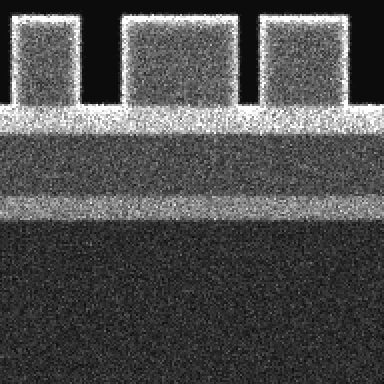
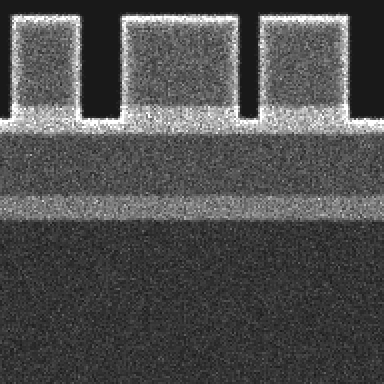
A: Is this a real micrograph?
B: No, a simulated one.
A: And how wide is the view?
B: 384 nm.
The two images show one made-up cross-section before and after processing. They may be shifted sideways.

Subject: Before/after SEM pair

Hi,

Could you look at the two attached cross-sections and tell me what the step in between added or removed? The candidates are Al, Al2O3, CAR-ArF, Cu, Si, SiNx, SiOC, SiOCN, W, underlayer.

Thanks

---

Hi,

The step removed W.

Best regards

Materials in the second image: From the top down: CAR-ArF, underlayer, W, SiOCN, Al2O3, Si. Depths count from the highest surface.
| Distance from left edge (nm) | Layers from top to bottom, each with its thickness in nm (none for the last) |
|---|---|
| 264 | CAR-ArF 70, underlayer 20, W 28, SiOCN 62, Al2O3 24, Si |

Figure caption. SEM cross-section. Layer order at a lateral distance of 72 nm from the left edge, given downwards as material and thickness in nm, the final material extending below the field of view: CAR-ArF 70, underlayer 20, W 28, SiOCN 62, Al2O3 24, Si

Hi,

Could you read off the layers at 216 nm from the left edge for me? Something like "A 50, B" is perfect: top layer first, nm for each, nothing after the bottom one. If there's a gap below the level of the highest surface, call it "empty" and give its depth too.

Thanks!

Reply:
CAR-ArF 70, underlayer 20, W 28, SiOCN 62, Al2O3 24, Si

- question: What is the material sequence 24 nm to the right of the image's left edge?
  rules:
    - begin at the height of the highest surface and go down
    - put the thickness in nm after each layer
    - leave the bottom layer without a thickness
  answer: CAR-ArF 70, underlayer 20, W 28, SiOCN 62, Al2O3 24, Si